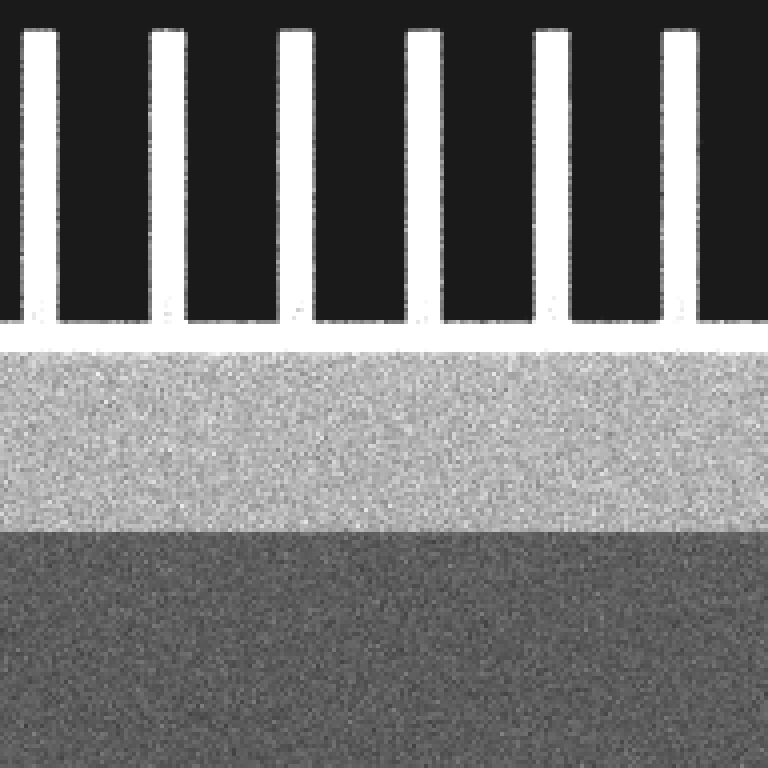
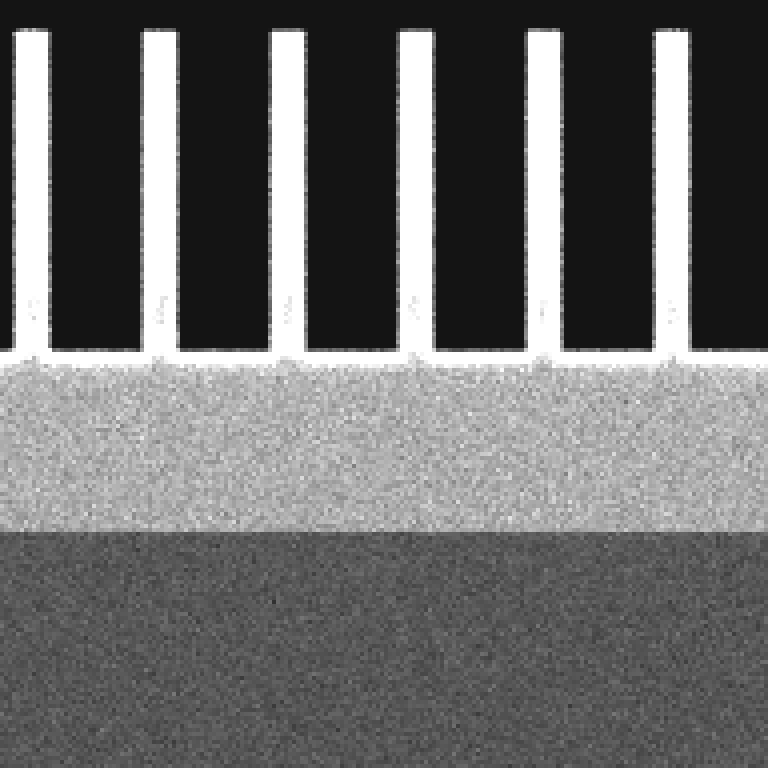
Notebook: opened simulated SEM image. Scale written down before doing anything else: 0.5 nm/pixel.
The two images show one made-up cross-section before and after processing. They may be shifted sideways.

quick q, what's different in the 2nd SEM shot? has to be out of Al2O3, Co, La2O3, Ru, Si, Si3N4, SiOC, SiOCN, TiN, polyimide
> Co removed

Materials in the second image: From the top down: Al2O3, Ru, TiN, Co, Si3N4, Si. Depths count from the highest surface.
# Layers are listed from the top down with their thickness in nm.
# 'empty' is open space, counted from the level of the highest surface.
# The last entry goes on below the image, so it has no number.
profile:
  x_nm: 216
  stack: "empty 160, Si3N4 90, Si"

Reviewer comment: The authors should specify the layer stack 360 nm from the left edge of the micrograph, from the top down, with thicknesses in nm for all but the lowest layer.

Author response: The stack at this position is empty 160, Si3N4 90, Si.